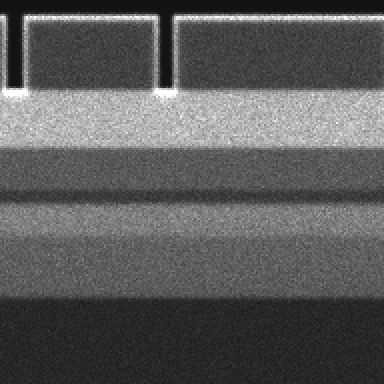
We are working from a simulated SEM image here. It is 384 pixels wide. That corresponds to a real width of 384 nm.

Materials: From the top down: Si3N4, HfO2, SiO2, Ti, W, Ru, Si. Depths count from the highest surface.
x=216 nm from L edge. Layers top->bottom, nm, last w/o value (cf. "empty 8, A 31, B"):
Si3N4 74, HfO2 58, SiO2 42, Ti 14, W 32, Ru 62, Si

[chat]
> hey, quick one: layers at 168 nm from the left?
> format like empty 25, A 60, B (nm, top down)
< empty 74, HfO2 58, SiO2 42, Ti 14, W 32, Ru 62, Si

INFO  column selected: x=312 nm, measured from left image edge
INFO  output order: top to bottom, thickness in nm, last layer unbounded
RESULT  Si3N4 74, HfO2 58, SiO2 42, Ti 14, W 32, Ru 62, Si